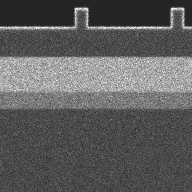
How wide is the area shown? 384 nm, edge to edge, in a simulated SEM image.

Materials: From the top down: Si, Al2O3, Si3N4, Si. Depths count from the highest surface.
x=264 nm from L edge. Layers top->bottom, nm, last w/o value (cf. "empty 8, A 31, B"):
empty 38, Si 60, Al2O3 70, Si3N4 34, Si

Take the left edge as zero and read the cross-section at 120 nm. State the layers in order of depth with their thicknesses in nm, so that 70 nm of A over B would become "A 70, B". empty 38, Si 60, Al2O3 70, Si3N4 34, Si